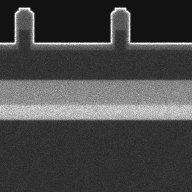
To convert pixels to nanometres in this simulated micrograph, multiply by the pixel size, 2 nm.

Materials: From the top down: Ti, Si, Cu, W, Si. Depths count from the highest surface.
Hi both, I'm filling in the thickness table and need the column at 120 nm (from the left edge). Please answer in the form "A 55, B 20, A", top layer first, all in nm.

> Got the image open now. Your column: empty 70, Ti 14, Si 60, Cu 50, W 30, Si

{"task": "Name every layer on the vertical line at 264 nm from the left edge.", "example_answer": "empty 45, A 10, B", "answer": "empty 70, Ti 14, Si 60, Cu 50, W 30, Si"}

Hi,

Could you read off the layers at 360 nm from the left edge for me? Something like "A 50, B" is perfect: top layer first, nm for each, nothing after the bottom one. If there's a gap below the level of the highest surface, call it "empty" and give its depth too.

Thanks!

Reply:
empty 70, Ti 14, Si 60, Cu 50, W 30, Si